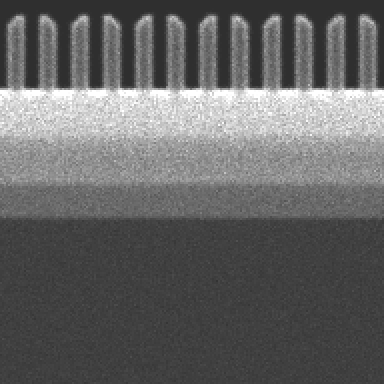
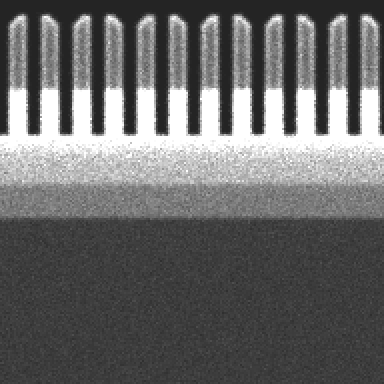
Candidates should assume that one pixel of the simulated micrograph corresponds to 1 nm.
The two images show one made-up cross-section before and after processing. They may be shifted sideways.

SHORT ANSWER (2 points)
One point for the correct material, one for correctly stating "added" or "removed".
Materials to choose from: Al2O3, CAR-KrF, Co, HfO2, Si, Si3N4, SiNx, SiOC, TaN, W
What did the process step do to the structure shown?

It removed HfO2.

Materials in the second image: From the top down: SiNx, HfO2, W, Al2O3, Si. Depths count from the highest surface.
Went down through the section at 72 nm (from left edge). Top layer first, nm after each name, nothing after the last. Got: empty 120, W 48, Al2O3 34, Si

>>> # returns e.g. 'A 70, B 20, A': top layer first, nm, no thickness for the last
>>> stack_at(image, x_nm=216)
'SiNx 74, HfO2 46, W 48, Al2O3 34, Si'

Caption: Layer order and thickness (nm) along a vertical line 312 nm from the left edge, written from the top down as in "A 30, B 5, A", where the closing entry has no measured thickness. empty 8, SiNx 66, HfO2 46, W 48, Al2O3 34, Si